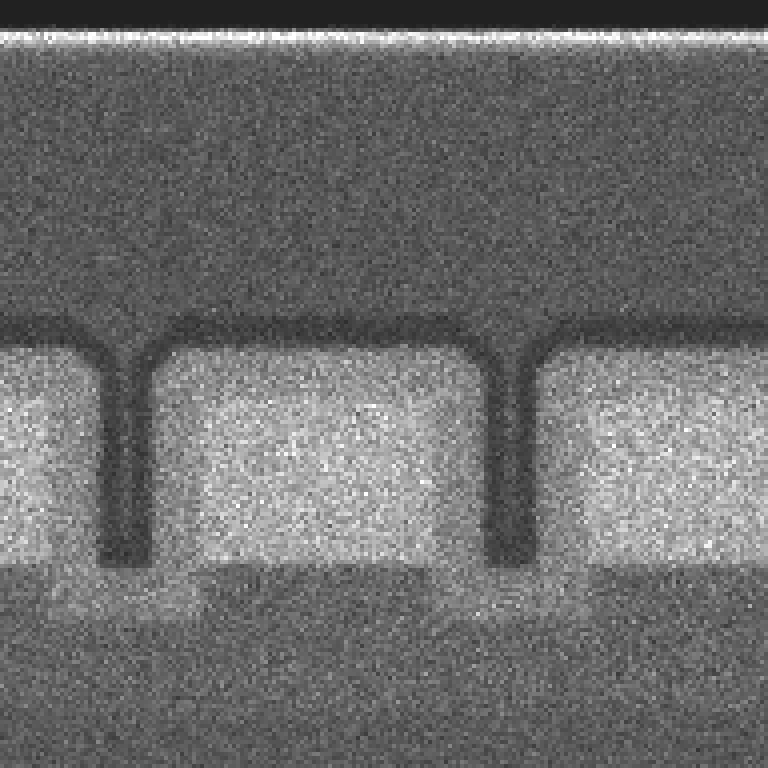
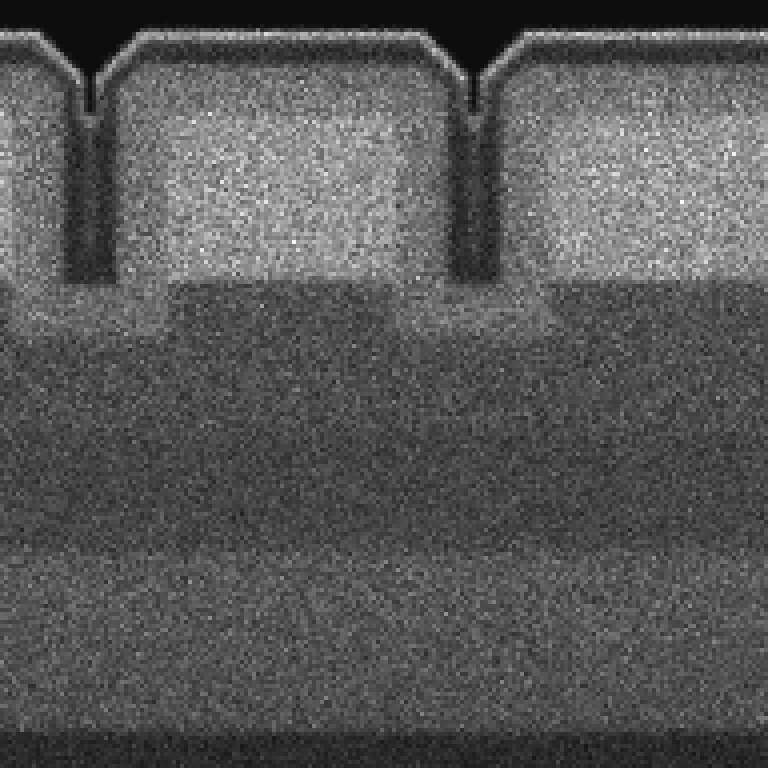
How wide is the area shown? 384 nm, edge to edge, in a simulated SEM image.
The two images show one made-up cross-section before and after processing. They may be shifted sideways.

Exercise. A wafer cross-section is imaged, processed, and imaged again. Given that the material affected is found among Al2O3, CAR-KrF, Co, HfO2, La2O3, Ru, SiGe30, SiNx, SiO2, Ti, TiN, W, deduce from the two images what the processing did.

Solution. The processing removed SiO2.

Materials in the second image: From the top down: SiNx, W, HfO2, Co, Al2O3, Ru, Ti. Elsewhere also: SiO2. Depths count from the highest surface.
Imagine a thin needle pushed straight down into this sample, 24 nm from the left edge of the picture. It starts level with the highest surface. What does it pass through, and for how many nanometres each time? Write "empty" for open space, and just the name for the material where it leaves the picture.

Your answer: empty 6, SiNx 16, W 130, Co 46, Al2O3 62, Ru 90, Ti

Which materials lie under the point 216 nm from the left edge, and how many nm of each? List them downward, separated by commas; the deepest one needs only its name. empty 6, SiNx 16, W 130, Co 46, Al2O3 62, Ru 90, Ti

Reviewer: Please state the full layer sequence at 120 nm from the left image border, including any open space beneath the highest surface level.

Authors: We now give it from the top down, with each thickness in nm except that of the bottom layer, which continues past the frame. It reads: SiNx 16, W 26, HfO2 82, Co 74, Al2O3 62, Ru 90, Ti